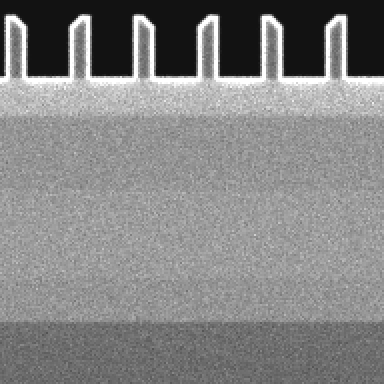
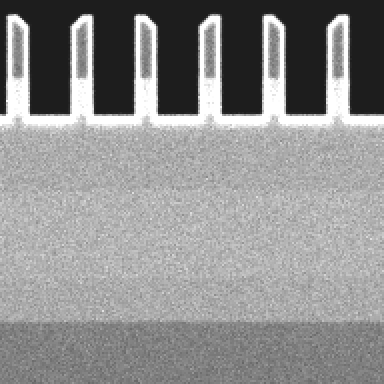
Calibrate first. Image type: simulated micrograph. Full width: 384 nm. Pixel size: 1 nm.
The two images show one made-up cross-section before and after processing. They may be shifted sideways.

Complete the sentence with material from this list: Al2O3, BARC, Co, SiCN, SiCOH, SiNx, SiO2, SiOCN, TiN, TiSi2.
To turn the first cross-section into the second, Co must be removed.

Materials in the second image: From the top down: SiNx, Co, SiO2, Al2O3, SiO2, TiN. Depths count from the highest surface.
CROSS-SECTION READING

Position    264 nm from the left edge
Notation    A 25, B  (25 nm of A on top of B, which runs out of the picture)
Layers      SiNx 62, Co 38, SiO2 74, Al2O3 88, SiO2 44, TiN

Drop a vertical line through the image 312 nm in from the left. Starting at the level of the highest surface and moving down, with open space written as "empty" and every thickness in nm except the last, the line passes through empty 100, SiO2 74, Al2O3 88, SiO2 44, TiN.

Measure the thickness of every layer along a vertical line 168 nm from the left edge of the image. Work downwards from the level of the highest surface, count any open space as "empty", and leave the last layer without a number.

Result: empty 100, SiO2 74, Al2O3 88, SiO2 44, TiN